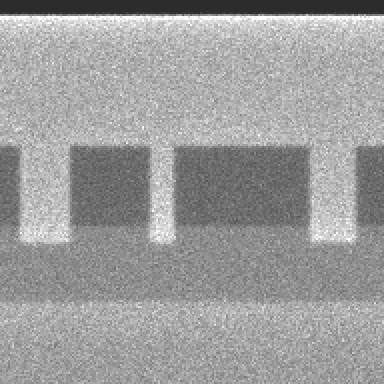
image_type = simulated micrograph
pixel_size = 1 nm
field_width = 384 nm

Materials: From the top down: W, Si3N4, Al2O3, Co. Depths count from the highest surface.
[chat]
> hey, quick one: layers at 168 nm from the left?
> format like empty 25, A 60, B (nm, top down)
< W 226, Al2O3 60, Co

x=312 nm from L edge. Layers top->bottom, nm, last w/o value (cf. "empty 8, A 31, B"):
W 226, Al2O3 60, Co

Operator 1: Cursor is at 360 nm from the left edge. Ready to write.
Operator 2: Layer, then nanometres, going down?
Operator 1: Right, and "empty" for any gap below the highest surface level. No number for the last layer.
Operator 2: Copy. W 130, Si3N4 80, Al2O3 76, Co